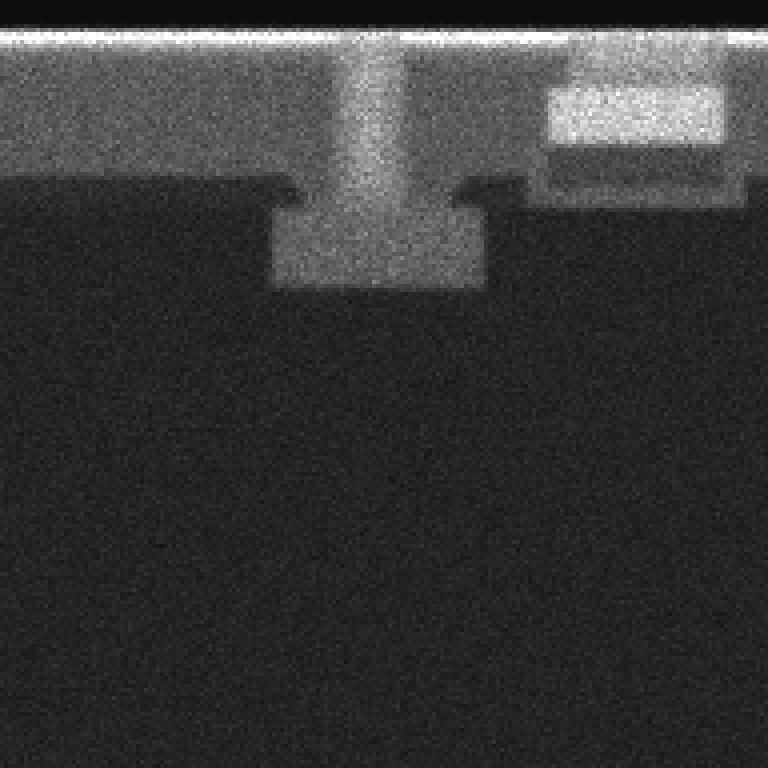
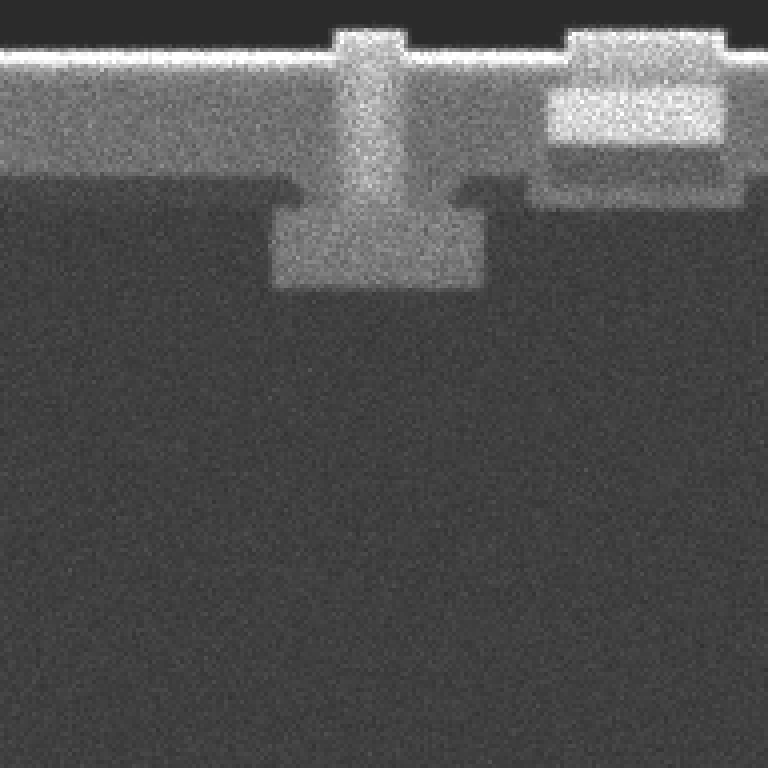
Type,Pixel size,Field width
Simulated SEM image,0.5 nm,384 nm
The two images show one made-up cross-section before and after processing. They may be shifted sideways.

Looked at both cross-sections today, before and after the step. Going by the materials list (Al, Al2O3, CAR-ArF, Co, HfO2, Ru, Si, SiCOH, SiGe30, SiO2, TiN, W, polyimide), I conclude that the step removed SiO2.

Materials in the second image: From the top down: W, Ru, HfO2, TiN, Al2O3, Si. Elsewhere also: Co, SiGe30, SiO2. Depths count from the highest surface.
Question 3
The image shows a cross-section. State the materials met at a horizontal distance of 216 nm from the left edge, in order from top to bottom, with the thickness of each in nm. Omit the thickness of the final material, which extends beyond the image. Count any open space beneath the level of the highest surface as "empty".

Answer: empty 10, SiO2 78, Co 40, Si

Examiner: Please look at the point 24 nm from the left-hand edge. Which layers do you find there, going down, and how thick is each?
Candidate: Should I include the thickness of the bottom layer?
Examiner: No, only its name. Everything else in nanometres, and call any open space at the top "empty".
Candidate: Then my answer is empty 10, SiO2 62, SiGe30 16, Si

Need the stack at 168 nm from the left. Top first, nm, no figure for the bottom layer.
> Ru 88, Co 40, Si